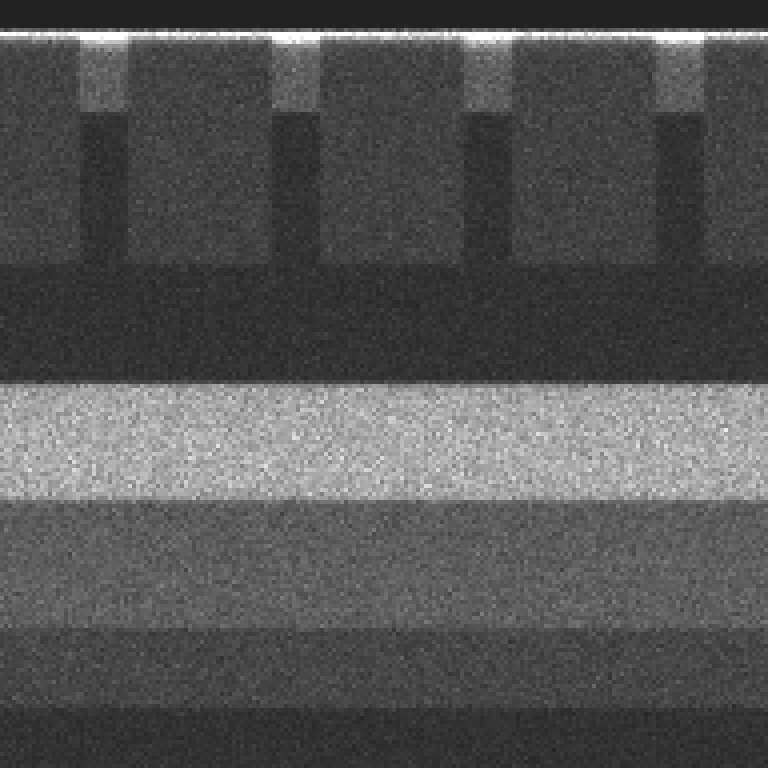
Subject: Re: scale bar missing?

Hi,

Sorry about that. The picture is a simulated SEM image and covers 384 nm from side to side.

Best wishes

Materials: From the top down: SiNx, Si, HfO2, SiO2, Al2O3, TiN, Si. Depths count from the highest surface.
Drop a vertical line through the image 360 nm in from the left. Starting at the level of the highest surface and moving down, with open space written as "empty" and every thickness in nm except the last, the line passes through SiNx 116, Si 60, HfO2 58, SiO2 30, Al2O3 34, TiN 40, Si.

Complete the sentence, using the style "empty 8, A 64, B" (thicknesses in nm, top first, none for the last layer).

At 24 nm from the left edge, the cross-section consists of SiNx 116, Si 60, HfO2 58, SiO2 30, Al2O3 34, TiN 40, Si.